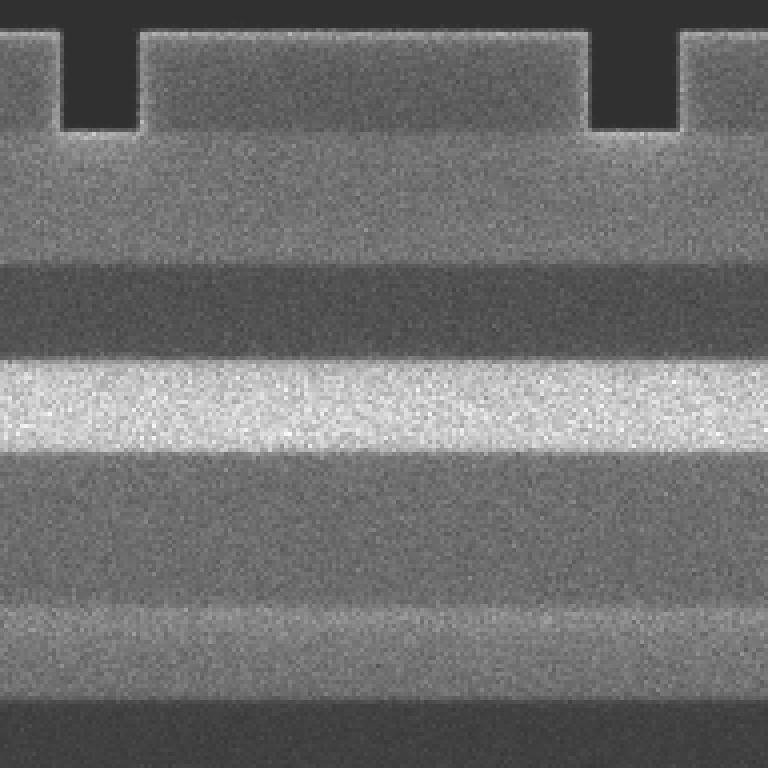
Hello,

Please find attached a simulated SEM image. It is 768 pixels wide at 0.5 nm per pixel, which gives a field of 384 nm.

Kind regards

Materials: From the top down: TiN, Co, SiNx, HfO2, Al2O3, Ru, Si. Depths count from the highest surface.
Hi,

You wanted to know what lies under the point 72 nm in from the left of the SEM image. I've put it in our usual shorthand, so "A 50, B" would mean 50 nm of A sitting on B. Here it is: TiN 50, Co 66, SiNx 48, HfO2 46, Al2O3 78, Ru 46, Si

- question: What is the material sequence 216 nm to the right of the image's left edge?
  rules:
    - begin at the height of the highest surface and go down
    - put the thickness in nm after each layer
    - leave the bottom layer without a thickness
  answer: TiN 50, Co 66, SiNx 48, HfO2 46, Al2O3 78, Ru 46, Si